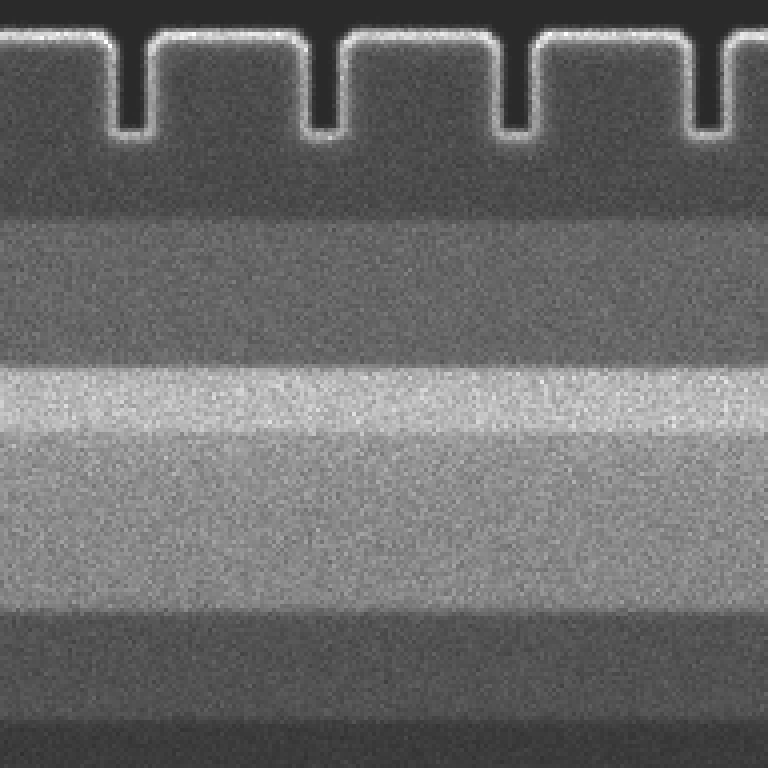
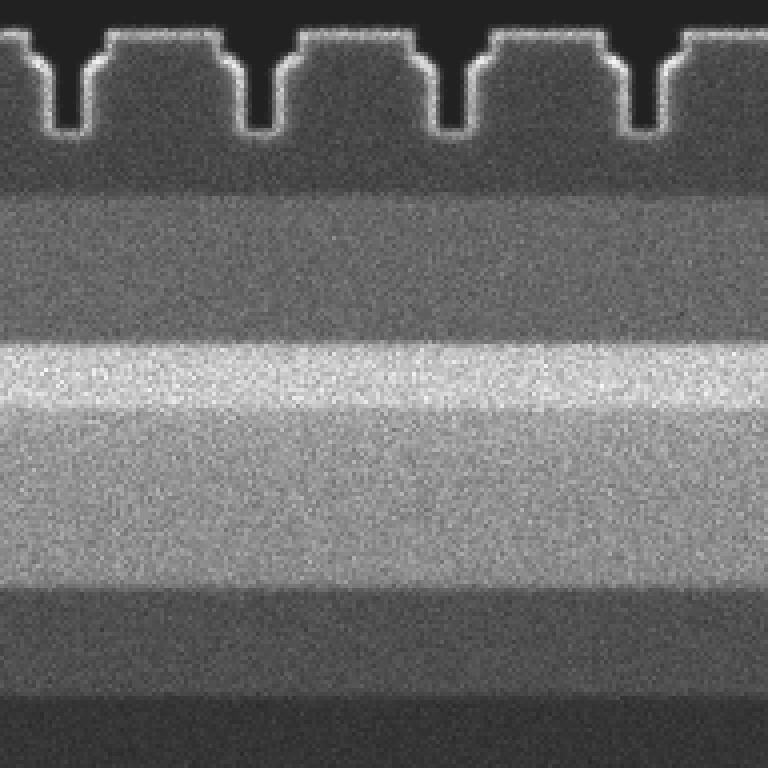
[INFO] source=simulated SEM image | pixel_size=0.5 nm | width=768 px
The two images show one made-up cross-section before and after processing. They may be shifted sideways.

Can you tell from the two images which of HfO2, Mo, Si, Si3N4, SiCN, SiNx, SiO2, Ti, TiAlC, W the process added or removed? Yes, it removed Si3N4.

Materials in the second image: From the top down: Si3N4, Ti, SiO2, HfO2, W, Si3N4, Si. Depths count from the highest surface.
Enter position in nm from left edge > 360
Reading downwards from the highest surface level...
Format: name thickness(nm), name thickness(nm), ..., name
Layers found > Ti 82, SiO2 74, HfO2 32, W 90, Si3N4 54, Si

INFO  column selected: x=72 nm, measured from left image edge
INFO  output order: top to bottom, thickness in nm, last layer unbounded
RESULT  Ti 82, SiO2 74, HfO2 32, W 90, Si3N4 54, Si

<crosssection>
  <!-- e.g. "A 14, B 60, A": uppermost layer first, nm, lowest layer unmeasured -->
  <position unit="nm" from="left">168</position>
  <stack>Ti 82, SiO2 74, HfO2 32, W 90, Si3N4 54, Si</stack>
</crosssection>